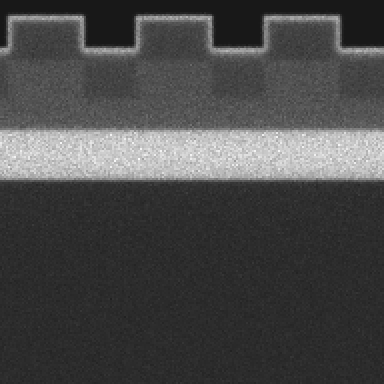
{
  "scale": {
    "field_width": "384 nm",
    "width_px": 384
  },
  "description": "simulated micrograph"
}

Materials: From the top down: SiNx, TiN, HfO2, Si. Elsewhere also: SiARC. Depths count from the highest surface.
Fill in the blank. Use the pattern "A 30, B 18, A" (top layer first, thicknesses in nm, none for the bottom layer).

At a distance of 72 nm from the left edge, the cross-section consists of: SiNx 44, TiN 70, HfO2 50, Si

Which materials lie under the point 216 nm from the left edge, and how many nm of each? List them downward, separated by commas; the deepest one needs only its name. empty 32, SiARC 50, TiN 32, HfO2 50, Si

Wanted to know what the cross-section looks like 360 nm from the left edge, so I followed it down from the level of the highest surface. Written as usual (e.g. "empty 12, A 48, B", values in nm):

empty 32, SiARC 50, TiN 32, HfO2 50, Si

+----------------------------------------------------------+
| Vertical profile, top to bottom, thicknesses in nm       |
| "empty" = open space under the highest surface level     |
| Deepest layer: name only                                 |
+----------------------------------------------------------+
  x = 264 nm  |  SiNx 44, TiN 70, HfO2 50, Si